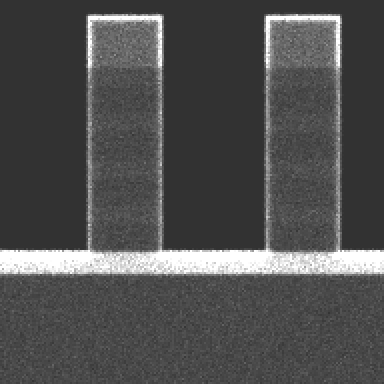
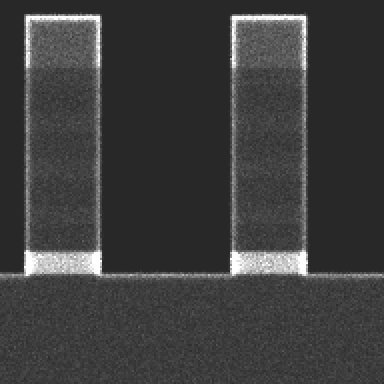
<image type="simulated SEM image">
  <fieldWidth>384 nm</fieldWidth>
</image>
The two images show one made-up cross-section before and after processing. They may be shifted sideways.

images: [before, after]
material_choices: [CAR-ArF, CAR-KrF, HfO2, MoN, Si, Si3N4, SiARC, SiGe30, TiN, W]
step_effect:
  removed: HfO2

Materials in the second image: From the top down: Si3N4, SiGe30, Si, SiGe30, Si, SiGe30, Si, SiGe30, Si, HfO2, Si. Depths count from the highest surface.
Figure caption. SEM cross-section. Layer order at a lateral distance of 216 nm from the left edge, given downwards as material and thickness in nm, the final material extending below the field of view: empty 258, Si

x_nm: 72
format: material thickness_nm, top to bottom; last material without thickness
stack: Si3N4 52, SiGe30 18, Si 28, SiGe30 18, Si 28, SiGe30 18, Si 28, SiGe30 18, Si 28, HfO2 22, Si